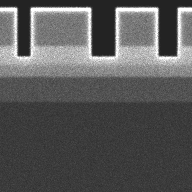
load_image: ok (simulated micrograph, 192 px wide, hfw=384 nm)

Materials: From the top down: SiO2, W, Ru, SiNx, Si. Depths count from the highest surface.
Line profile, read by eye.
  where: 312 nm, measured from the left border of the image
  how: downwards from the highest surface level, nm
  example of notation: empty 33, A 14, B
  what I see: SiO2 76, W 38, Ru 24, SiNx 50, Si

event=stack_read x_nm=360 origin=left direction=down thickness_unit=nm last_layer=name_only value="SiO2 76, W 38, Ru 24, SiNx 50, Si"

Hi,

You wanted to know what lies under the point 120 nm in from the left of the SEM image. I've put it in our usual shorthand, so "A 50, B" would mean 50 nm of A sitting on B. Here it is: SiO2 76, W 38, Ru 24, SiNx 50, Si